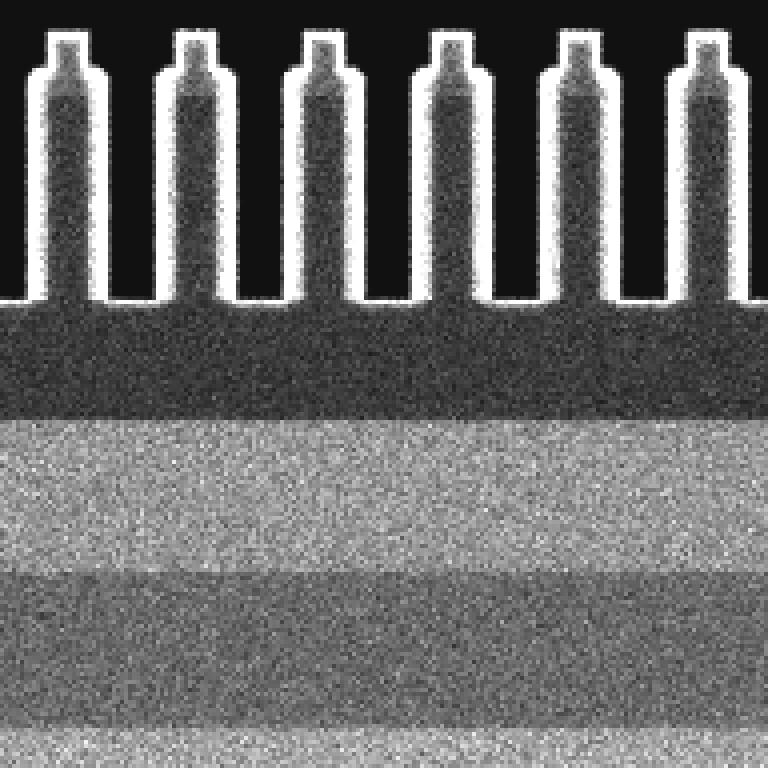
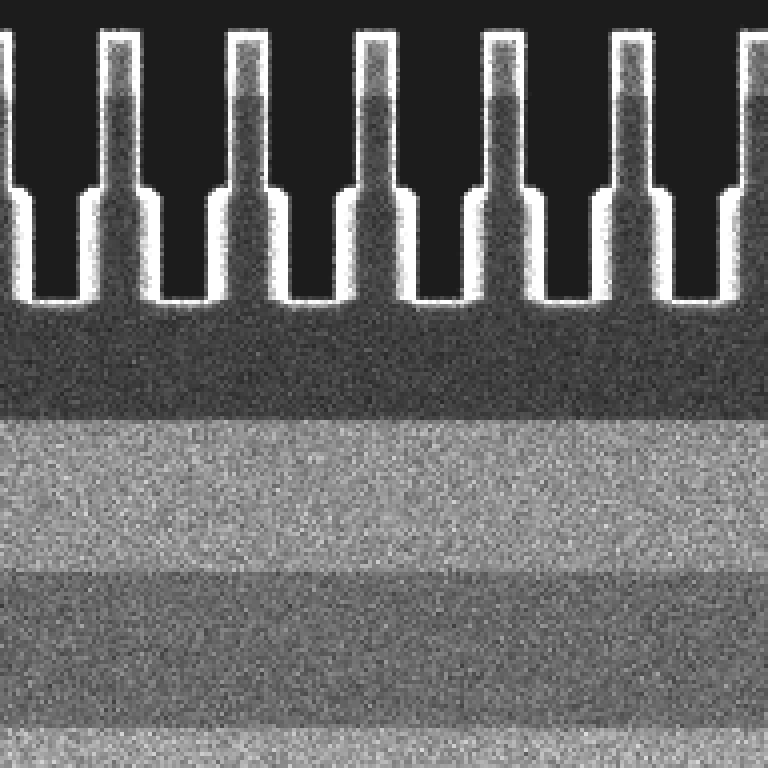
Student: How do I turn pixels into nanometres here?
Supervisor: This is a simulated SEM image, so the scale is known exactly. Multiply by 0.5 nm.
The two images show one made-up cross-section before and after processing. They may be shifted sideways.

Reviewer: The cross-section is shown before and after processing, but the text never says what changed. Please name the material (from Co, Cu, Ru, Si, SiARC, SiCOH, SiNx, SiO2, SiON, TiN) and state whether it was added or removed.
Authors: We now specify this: SiO2, removed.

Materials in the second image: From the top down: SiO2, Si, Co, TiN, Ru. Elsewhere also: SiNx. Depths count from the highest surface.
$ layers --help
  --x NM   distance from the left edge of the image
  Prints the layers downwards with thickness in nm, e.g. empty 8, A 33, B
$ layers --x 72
empty 78, SiO2 56, Si 60, Co 76, TiN 78, Ru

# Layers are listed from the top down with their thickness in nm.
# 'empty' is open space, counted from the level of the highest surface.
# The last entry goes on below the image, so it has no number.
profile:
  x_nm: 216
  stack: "empty 134, Si 60, Co 76, TiN 78, Ru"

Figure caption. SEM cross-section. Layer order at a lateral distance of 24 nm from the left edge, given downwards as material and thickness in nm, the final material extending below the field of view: empty 134, Si 60, Co 76, TiN 78, Ru